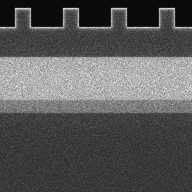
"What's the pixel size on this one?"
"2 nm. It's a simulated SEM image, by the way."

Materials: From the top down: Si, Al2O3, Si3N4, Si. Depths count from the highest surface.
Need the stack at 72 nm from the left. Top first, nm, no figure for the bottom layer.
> empty 38, Si 60, Al2O3 86, Si3N4 26, Si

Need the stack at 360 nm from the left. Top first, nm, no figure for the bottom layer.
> empty 38, Si 60, Al2O3 86, Si3N4 26, Si